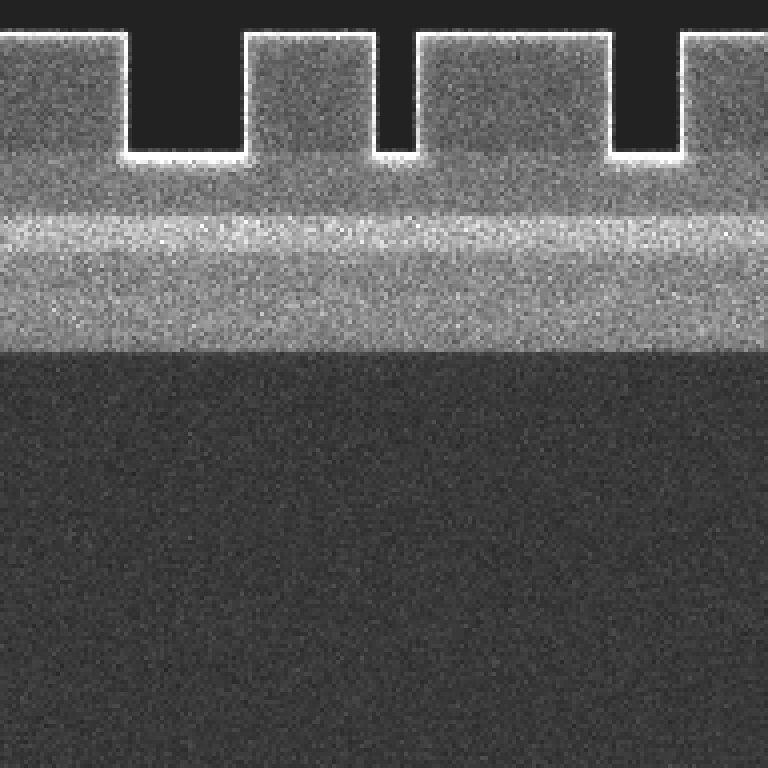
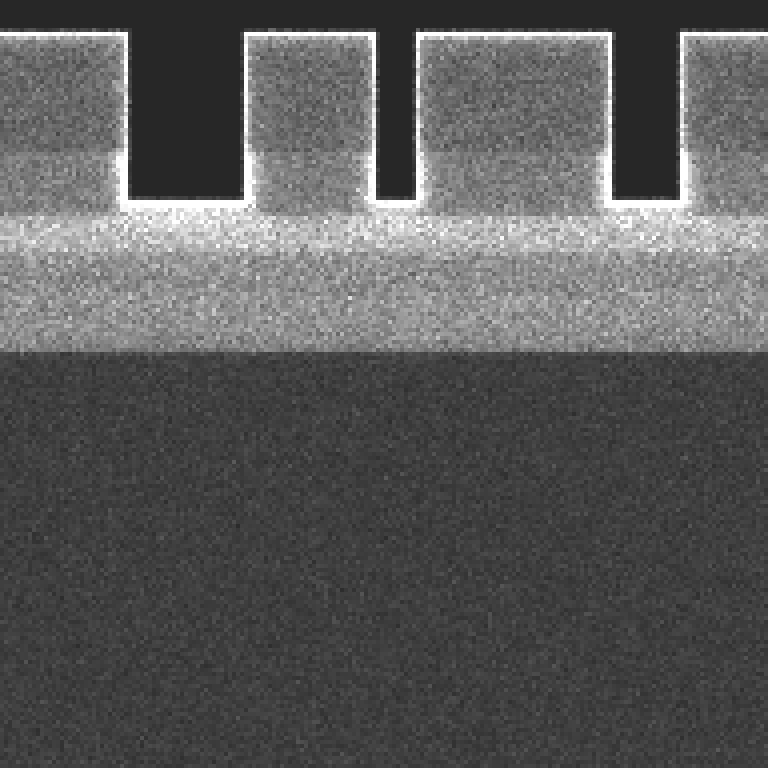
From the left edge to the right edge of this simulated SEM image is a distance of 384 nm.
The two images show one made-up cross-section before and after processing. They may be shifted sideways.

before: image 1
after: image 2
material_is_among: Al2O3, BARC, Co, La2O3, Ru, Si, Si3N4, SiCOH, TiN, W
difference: Al2O3, removed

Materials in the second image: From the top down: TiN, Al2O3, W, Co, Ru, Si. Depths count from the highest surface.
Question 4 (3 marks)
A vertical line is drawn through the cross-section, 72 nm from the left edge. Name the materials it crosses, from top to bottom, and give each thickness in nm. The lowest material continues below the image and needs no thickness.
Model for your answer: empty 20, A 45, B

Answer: empty 84, Al2O3 8, W 18, Co 20, Ru 30, Si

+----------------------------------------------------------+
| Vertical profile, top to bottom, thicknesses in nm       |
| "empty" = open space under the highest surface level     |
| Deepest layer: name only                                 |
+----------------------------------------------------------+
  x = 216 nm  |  TiN 60, Al2O3 32, W 18, Co 20, Ru 30, Si